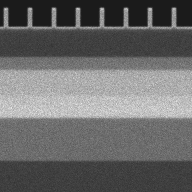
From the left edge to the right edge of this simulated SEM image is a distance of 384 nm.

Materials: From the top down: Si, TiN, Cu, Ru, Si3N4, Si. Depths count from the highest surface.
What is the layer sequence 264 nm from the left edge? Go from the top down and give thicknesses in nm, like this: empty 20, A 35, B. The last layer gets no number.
empty 38, Si 60, TiN 26, Cu 52, Ru 44, Si3N4 86, Si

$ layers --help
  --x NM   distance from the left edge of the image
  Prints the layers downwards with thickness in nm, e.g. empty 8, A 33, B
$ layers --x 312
empty 38, Si 60, TiN 26, Cu 52, Ru 44, Si3N4 86, Si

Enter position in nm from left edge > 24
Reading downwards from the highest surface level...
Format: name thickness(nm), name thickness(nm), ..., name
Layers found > empty 38, Si 60, TiN 26, Cu 52, Ru 44, Si3N4 86, Si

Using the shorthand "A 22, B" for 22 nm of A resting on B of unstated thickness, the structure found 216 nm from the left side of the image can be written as empty 38, Si 60, TiN 26, Cu 52, Ru 44, Si3N4 86, Si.